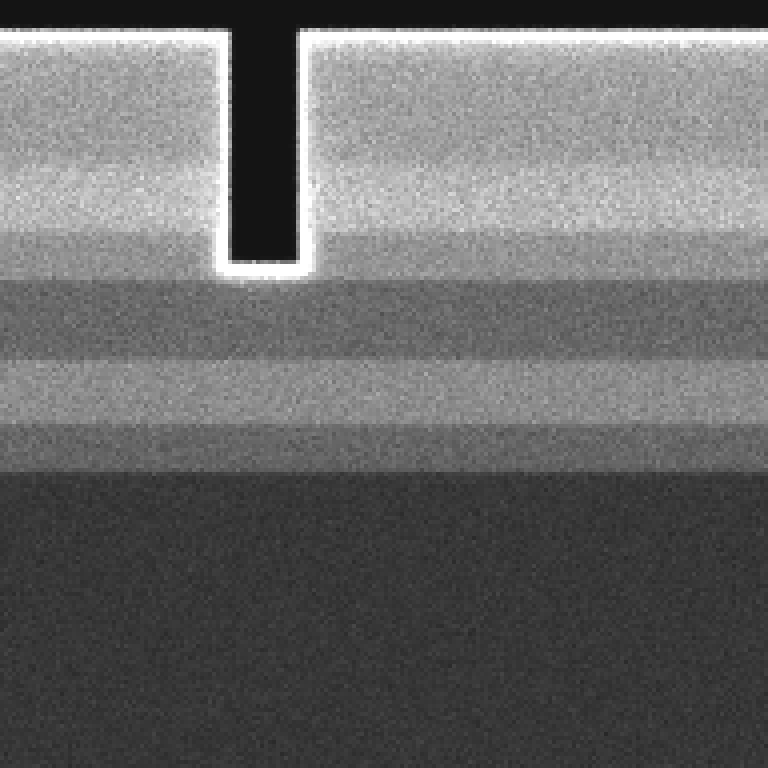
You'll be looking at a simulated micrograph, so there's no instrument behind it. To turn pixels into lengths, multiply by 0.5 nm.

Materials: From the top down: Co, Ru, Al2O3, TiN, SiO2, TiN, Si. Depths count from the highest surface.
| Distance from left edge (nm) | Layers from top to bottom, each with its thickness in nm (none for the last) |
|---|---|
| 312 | Co 66, Ru 34, Al2O3 24, TiN 40, SiO2 32, TiN 24, Si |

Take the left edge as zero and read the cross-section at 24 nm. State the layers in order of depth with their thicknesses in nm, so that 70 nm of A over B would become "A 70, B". Co 66, Ru 34, Al2O3 24, TiN 40, SiO2 32, TiN 24, Si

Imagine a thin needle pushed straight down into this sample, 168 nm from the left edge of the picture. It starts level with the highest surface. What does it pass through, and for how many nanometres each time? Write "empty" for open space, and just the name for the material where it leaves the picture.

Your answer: Co 66, Ru 34, Al2O3 24, TiN 40, SiO2 32, TiN 24, Si